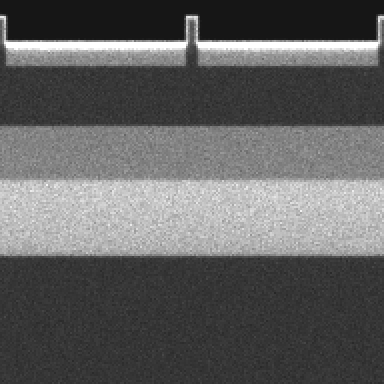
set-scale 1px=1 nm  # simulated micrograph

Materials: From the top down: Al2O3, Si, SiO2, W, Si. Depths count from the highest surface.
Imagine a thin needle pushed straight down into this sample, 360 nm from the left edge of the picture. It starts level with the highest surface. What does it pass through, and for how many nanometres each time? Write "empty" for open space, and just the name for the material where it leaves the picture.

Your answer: empty 26, Al2O3 24, Si 60, SiO2 54, W 76, Si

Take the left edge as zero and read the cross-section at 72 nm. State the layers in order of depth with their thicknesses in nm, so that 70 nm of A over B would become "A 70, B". empty 26, Al2O3 24, Si 60, SiO2 54, W 76, Si